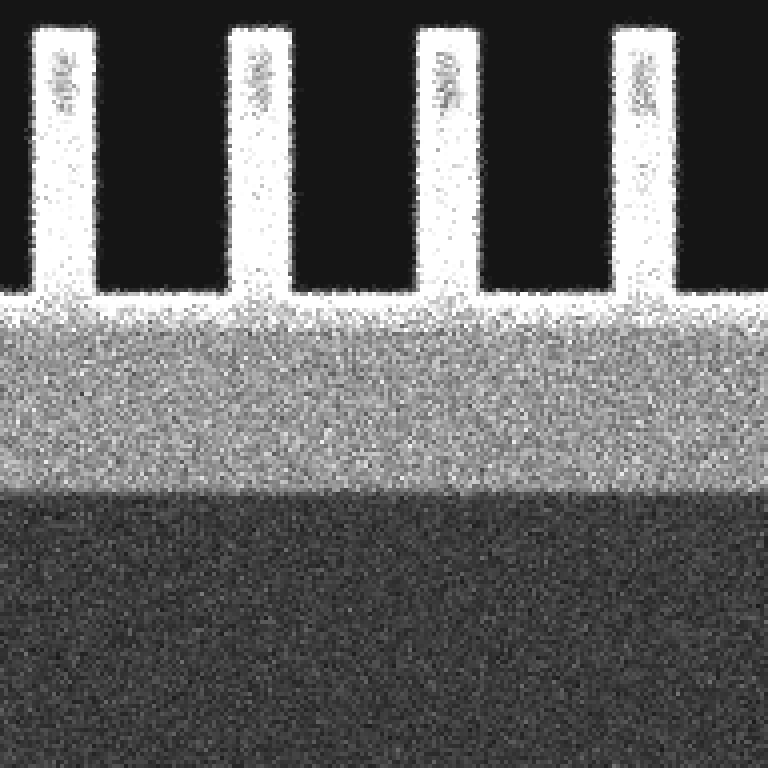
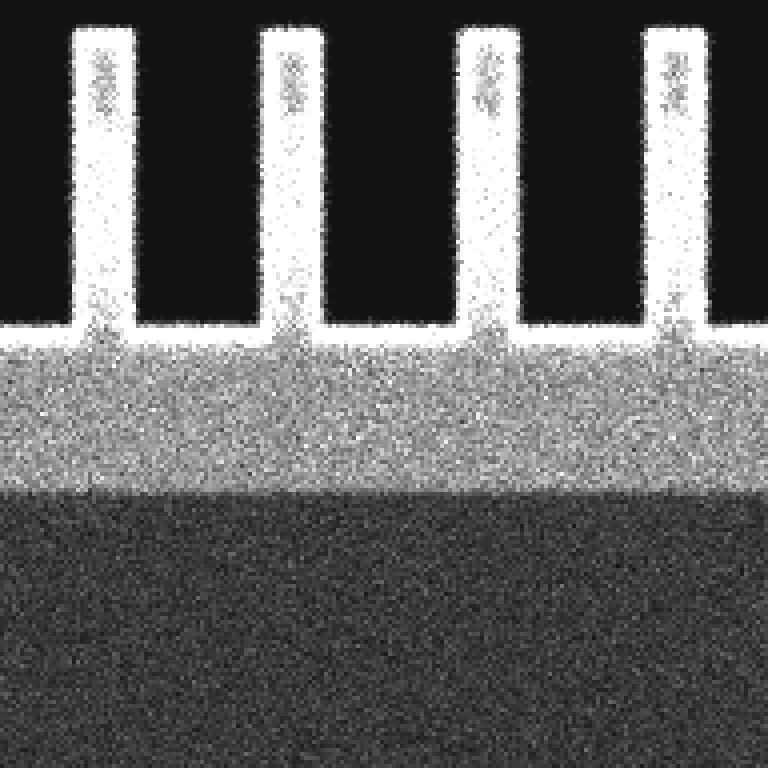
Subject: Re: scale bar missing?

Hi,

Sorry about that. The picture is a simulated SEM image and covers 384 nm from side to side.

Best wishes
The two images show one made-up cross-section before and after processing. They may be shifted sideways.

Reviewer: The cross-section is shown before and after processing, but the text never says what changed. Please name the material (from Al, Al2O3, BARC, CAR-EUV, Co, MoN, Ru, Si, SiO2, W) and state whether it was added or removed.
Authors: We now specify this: Co, removed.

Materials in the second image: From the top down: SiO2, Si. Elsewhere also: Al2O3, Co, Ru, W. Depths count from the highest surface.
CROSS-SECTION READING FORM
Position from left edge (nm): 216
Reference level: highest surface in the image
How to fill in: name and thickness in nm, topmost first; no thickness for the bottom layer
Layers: empty 148, SiO2 82, Si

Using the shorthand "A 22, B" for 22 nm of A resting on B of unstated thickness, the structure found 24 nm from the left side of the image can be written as empty 148, SiO2 82, Si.